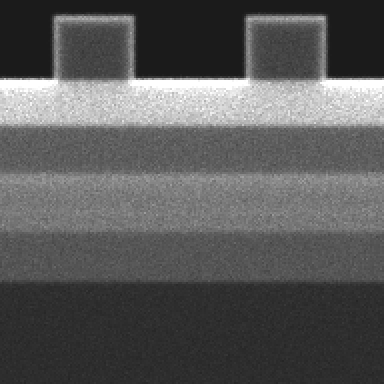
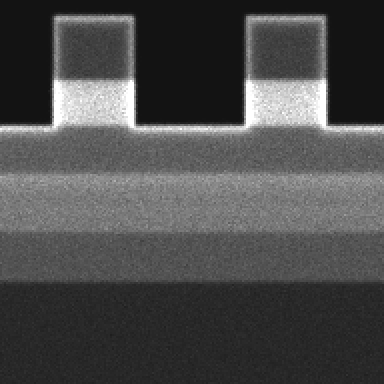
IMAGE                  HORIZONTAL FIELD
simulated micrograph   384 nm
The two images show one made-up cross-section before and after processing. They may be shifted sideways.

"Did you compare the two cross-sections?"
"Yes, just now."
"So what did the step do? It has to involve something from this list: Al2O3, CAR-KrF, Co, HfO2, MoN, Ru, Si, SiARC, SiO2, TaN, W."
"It removed HfO2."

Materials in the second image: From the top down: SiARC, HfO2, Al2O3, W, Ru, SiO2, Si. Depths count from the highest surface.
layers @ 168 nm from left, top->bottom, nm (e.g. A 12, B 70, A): empty 110, Al2O3 48, W 42, Ru 16, SiO2 50, Si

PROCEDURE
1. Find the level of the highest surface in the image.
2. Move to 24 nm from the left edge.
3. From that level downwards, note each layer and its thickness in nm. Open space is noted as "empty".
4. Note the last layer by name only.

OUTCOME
empty 110, Al2O3 48, W 42, Ru 16, SiO2 50, Si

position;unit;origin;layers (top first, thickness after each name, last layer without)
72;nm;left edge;SiARC 64, HfO2 46, Al2O3 48, W 42, Ru 16, SiO2 50, Si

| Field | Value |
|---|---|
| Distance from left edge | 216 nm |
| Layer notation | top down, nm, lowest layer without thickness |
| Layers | empty 110, Al2O3 48, W 42, Ru 16, SiO2 50, Si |